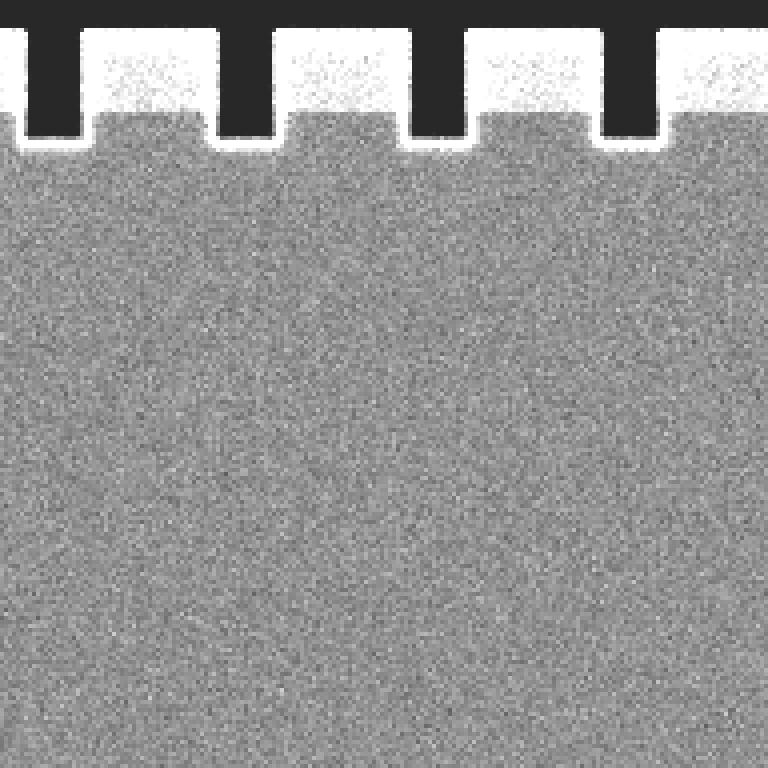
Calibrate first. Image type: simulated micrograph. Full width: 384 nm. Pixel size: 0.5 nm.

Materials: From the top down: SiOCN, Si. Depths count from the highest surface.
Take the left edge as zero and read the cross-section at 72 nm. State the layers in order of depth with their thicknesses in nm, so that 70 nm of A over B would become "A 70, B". SiOCN 40, Si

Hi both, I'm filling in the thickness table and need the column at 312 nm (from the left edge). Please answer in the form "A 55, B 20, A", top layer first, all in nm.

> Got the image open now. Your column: empty 54, Si